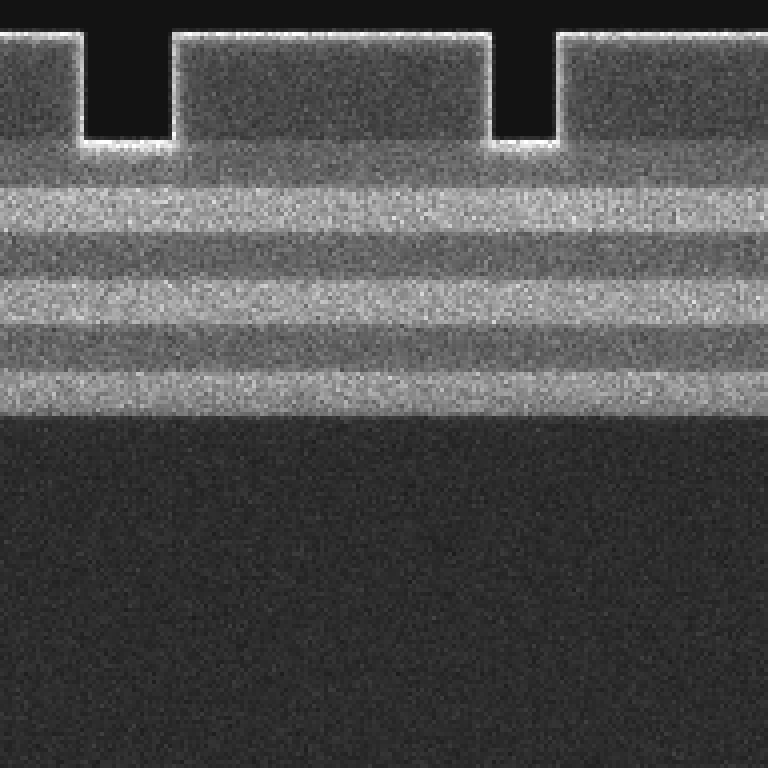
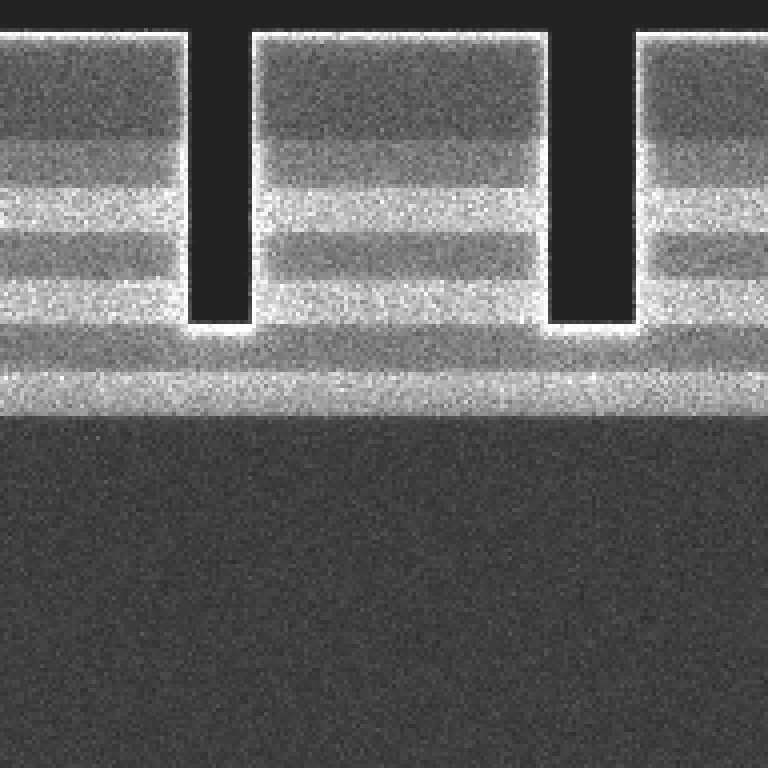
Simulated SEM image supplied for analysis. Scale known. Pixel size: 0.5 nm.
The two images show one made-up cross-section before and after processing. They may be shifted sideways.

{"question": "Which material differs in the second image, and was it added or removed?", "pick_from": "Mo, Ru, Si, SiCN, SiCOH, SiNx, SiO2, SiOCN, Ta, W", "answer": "SiO2 and W, removed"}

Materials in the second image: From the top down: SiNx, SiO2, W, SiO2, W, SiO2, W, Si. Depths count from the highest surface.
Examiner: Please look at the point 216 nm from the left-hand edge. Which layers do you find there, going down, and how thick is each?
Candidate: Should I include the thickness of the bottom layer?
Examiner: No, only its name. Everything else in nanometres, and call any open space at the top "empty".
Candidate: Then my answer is SiNx 54, SiO2 24, W 22, SiO2 24, W 22, SiO2 24, W 22, Si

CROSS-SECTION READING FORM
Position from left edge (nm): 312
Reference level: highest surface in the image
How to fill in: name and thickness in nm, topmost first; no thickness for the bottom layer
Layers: empty 146, SiO2 24, W 22, Si